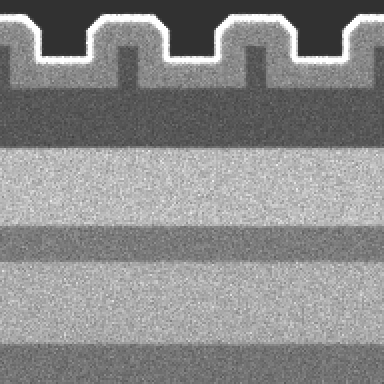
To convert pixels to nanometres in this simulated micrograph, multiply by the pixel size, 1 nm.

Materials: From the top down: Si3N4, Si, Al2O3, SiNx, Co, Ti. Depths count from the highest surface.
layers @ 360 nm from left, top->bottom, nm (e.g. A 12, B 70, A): Si3N4 72, Si 60, Al2O3 78, SiNx 36, Co 82, Ti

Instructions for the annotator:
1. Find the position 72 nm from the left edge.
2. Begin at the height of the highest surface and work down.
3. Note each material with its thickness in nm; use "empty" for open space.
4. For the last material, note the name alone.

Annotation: empty 42, Si3N4 30, Si 60, Al2O3 78, SiNx 36, Co 82, Ti